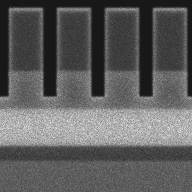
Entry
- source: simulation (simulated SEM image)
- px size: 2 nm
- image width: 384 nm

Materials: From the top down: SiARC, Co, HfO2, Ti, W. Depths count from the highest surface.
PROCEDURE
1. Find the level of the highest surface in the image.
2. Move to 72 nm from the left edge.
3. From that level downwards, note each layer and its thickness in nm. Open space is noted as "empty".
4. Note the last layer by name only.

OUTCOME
SiARC 126, Co 76, HfO2 74, Ti 30, W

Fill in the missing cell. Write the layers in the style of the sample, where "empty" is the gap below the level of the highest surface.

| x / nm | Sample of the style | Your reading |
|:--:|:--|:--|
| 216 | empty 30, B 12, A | SiARC 126, Co 76, HfO2 74, Ti 30, W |